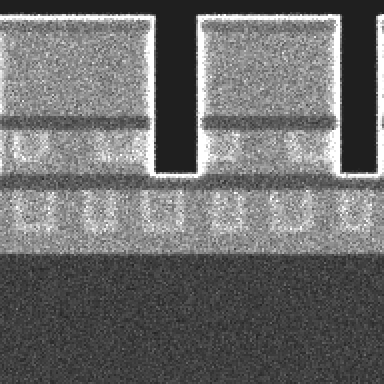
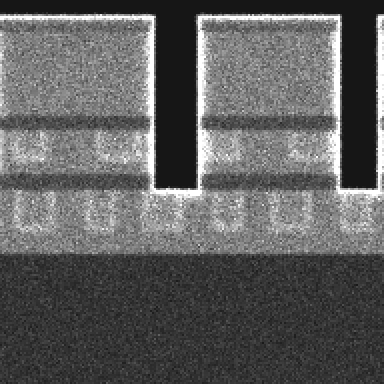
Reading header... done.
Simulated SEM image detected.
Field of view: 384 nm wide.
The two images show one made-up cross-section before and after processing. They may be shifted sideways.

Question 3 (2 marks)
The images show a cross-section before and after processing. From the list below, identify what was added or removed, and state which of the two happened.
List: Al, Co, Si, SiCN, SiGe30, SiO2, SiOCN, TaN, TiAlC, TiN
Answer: SiCN was removed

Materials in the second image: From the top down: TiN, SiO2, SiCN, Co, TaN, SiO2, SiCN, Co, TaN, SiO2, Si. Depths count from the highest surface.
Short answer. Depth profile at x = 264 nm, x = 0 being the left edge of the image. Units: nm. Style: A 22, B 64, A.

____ TiN 16, SiO2 84, SiCN 14, SiO2 44, SiCN 16, SiO2 64, Si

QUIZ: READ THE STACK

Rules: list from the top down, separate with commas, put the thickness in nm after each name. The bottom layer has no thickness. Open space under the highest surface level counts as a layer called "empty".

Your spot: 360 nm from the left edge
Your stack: empty 174, Co 34, TaN 8, SiO2 22, Si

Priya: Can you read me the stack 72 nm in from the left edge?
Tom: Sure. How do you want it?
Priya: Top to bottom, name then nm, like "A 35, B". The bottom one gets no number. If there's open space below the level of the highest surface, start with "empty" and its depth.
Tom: TiN 16, SiO2 84, SiCN 14, SiO2 44, SiCN 16, SiO2 64, Si